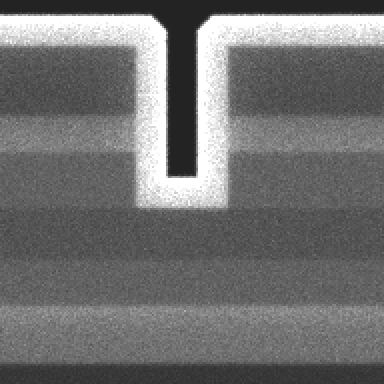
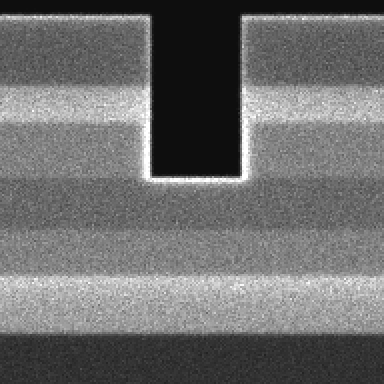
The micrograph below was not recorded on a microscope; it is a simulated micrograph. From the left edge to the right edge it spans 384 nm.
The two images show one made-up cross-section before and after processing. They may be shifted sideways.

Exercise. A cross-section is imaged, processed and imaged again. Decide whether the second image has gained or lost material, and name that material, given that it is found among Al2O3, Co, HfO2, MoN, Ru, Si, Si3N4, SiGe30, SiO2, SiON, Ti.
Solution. removed: HfO2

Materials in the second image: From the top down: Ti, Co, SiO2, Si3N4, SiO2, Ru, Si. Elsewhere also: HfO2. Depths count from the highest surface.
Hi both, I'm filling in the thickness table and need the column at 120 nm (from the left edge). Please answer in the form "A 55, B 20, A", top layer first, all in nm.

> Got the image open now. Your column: Ti 70, Co 36, SiO2 56, Si3N4 52, SiO2 46, Ru 58, Si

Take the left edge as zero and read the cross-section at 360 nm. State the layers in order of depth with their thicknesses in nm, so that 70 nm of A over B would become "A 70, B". Ti 70, Co 36, SiO2 56, Si3N4 52, SiO2 46, Ru 58, Si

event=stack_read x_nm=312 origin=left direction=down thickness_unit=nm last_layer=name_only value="Ti 70, Co 36, SiO2 56, Si3N4 52, SiO2 46, Ru 58, Si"